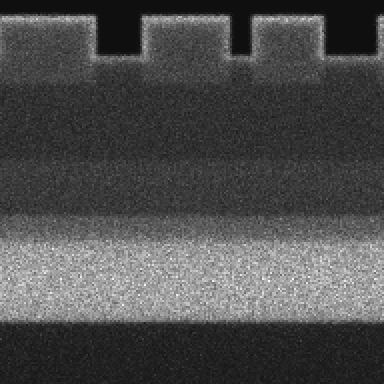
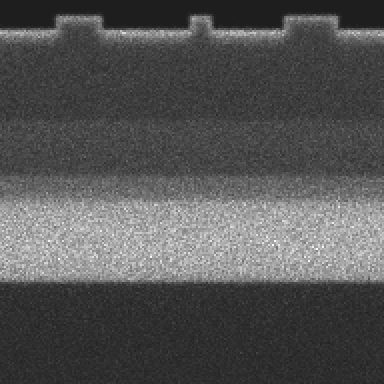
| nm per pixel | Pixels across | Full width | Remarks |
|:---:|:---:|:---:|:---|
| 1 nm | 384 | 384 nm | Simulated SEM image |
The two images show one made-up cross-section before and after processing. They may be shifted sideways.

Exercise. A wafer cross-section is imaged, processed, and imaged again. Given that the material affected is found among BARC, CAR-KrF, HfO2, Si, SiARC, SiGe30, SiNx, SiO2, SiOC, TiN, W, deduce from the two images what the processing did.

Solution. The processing removed SiO2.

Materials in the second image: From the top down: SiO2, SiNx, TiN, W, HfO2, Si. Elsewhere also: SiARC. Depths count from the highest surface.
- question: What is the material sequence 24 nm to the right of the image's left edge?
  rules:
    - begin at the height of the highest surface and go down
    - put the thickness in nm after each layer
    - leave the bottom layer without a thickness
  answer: empty 14, SiO2 14, SiNx 76, TiN 56, W 26, HfO2 80, Si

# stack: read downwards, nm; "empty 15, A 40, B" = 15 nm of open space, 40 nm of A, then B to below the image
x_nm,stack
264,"empty 14, SiO2 14, SiNx 76, TiN 56, W 26, HfO2 80, Si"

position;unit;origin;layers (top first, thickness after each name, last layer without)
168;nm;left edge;empty 14, SiO2 14, SiNx 76, TiN 56, W 26, HfO2 80, Si